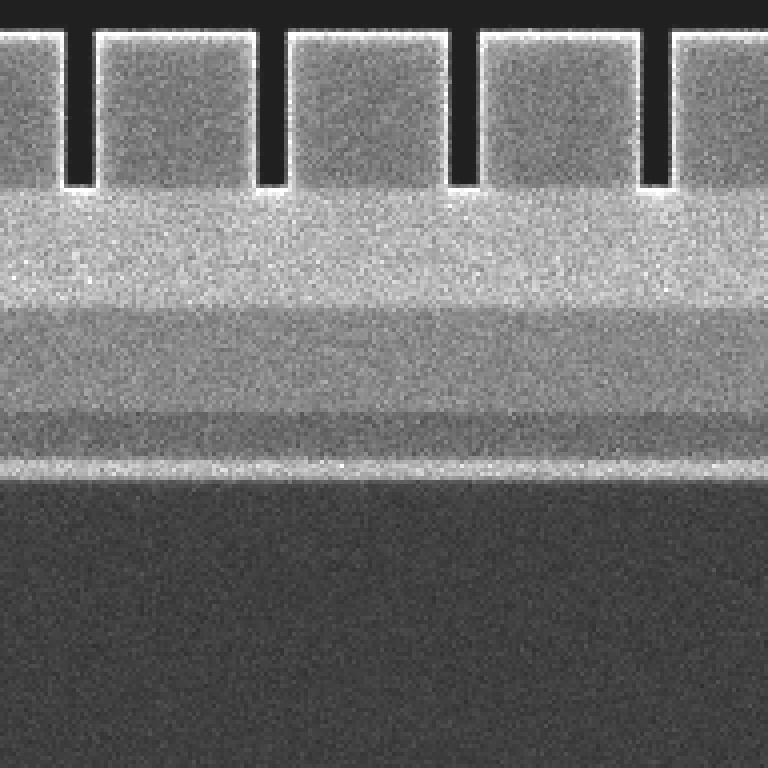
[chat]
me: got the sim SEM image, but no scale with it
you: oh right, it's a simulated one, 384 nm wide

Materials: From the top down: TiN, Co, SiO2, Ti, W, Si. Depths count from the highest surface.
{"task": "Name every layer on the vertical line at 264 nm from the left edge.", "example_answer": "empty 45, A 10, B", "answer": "TiN 78, Co 60, SiO2 52, Ti 24, W 10, Si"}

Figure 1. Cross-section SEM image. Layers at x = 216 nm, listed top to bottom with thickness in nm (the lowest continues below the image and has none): TiN 78, Co 60, SiO2 52, Ti 24, W 10, Si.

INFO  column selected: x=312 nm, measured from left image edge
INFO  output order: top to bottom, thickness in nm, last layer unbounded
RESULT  TiN 78, Co 60, SiO2 52, Ti 24, W 10, Si